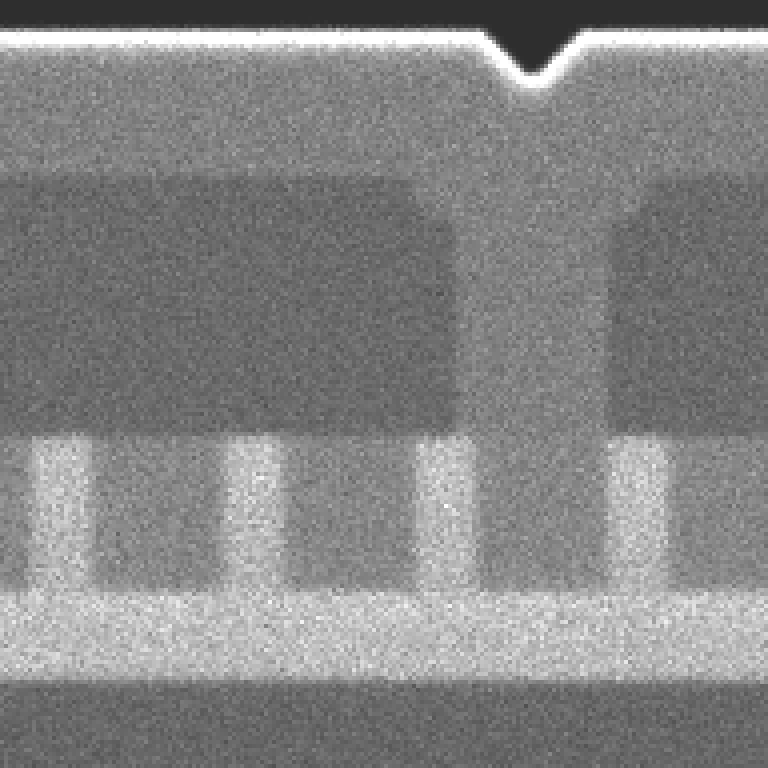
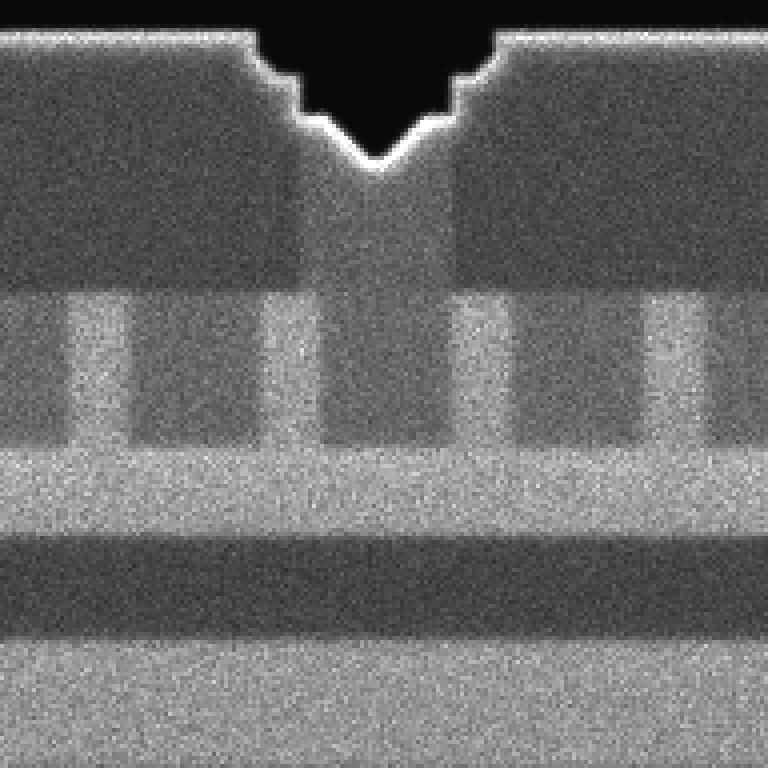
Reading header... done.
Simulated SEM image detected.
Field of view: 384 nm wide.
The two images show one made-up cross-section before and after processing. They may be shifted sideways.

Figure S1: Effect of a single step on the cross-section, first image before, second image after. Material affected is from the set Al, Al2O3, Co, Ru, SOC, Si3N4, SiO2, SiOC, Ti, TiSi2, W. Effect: removed SiO2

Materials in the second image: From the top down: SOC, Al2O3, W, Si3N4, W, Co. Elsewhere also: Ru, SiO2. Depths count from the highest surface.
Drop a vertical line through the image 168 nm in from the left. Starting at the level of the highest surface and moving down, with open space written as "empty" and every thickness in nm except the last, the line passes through empty 48, SiO2 82, Al2O3 78, W 44, Si3N4 52, W 62, Co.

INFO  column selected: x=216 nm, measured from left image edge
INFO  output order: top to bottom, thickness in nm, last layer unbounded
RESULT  empty 42, SiO2 88, Al2O3 78, W 44, Si3N4 52, W 62, Co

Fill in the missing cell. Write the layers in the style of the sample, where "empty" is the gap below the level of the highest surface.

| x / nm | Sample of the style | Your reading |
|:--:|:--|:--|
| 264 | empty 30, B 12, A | SOC 130, Al2O3 78, W 44, Si3N4 52, W 62, Co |